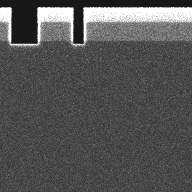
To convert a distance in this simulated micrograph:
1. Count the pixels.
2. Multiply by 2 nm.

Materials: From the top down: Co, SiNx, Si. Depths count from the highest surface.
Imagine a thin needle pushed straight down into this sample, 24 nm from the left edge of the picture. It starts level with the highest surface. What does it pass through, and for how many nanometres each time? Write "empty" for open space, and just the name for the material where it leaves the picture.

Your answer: empty 72, Si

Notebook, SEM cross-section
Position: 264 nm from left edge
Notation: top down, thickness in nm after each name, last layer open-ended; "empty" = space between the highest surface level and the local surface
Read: Co 28, SiNx 38, Si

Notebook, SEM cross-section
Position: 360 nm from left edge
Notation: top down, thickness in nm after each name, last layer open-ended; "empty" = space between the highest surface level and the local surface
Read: Co 28, SiNx 38, Si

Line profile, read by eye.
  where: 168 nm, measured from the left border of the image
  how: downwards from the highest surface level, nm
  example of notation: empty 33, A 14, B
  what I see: Co 28, SiNx 38, Si